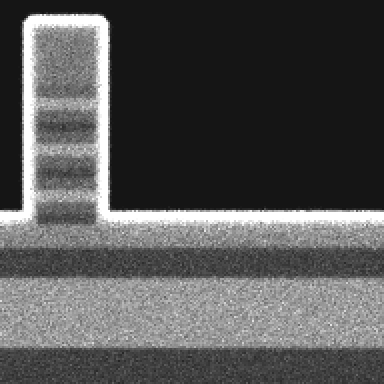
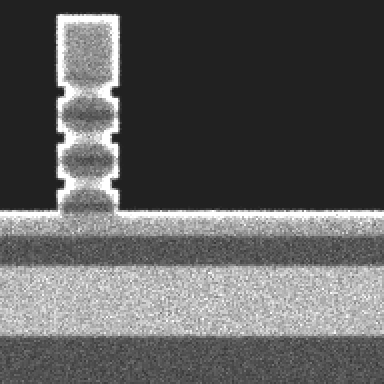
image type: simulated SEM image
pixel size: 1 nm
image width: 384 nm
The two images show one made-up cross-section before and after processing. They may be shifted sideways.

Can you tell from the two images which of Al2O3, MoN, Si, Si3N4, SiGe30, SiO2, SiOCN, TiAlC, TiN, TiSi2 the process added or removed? Yes, it removed Al2O3.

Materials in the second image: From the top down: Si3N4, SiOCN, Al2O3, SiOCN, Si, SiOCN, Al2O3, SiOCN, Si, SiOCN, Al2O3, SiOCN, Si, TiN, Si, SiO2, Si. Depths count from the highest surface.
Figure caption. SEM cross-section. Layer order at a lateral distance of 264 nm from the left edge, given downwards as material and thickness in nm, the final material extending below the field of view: empty 196, TiN 24, Si 30, SiO2 70, Si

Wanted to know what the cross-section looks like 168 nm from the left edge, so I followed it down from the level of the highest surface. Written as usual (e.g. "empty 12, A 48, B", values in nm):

empty 196, TiN 24, Si 30, SiO2 70, Si